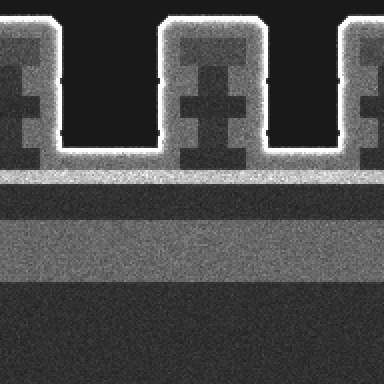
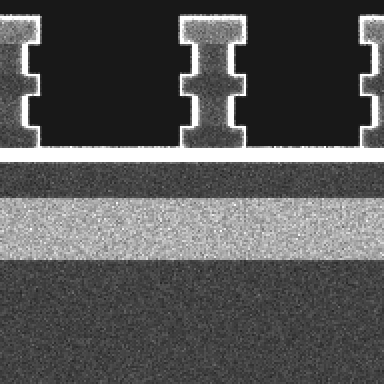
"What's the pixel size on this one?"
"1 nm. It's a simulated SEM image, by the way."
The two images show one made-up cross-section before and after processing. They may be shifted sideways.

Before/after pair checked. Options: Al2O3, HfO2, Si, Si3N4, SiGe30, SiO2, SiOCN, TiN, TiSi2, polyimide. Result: removed Al2O3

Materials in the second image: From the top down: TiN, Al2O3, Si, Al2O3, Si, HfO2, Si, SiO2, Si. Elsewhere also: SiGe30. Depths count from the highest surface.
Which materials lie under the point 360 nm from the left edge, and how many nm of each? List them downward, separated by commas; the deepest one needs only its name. TiN 28, empty 30, Si 22, empty 30, Si 22, HfO2 14, Si 36, SiO2 62, Si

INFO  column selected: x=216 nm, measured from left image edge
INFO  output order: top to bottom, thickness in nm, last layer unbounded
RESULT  TiN 28, SiGe30 30, Si 22, SiGe30 30, Si 22, HfO2 14, Si 36, SiO2 62, Si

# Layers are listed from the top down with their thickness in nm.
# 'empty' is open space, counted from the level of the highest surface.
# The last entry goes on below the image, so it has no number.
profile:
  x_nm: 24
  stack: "TiN 28, Al2O3 30, Si 22, Al2O3 30, Si 22, HfO2 14, Si 36, SiO2 62, Si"